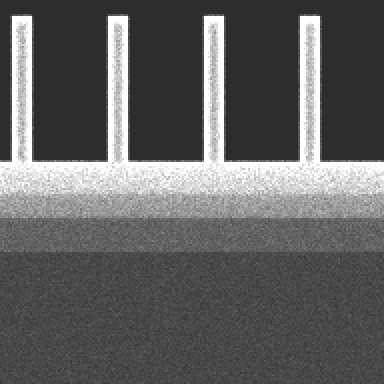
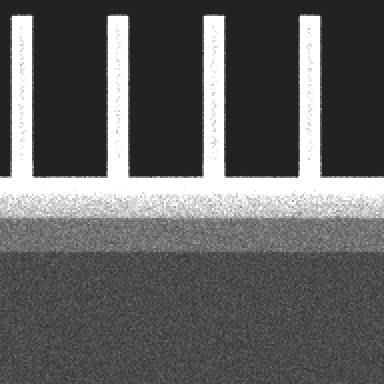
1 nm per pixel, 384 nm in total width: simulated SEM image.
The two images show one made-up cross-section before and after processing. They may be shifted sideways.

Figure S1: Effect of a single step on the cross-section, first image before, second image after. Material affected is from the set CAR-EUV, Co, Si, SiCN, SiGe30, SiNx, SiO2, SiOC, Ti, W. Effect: removed W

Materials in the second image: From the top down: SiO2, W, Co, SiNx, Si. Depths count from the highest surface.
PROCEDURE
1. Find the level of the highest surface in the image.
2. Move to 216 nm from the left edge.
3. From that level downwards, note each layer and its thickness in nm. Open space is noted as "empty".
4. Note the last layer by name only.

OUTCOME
SiO2 146, W 32, Co 24, SiNx 34, Si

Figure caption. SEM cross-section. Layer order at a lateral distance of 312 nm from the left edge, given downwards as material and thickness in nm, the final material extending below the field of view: SiO2 146, W 32, Co 24, SiNx 34, Si